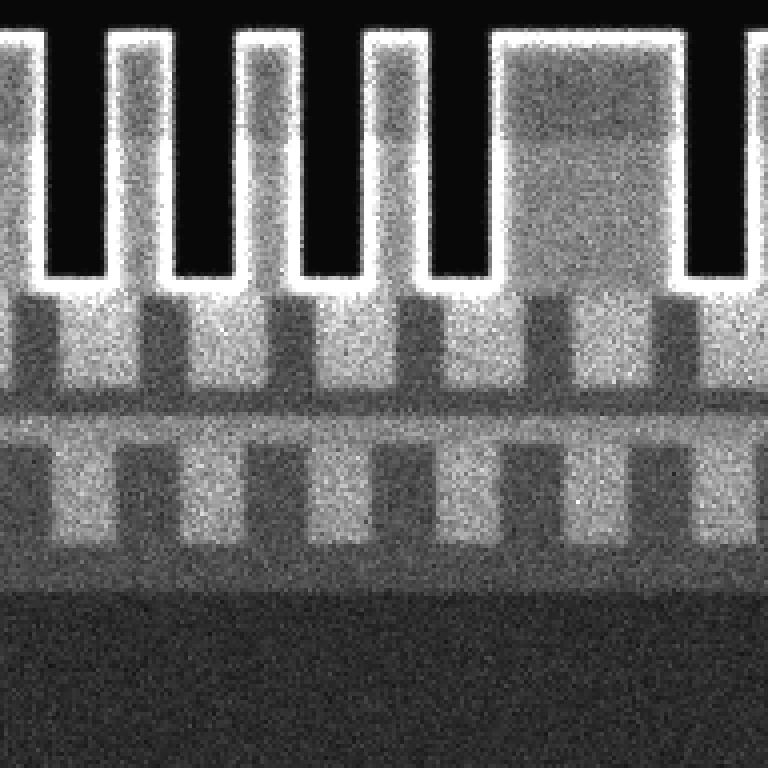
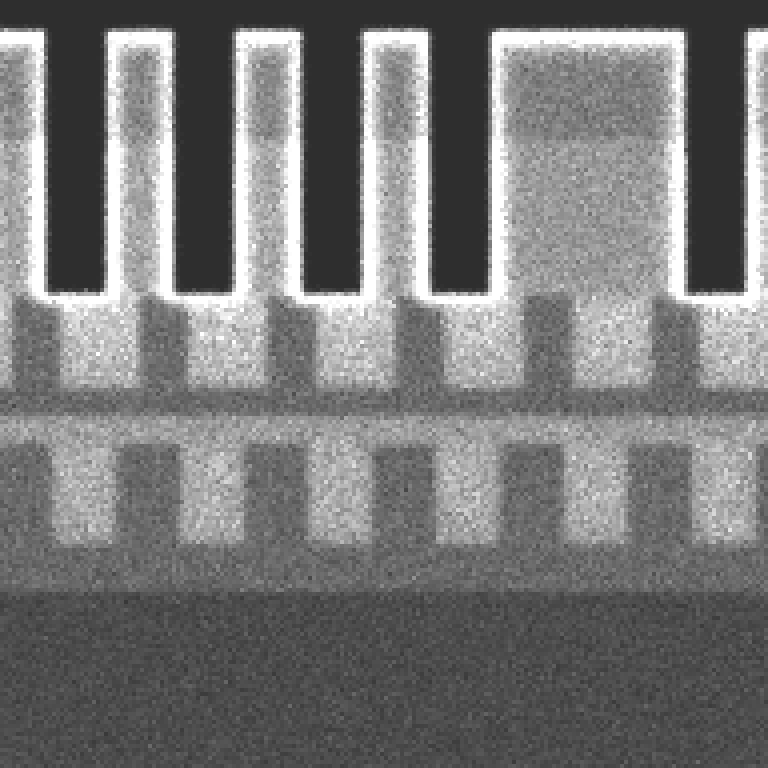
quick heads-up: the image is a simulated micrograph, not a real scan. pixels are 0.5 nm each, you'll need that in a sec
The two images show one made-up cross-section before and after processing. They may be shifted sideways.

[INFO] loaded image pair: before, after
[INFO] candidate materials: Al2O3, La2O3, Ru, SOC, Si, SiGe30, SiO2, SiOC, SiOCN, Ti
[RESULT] removed Al2O3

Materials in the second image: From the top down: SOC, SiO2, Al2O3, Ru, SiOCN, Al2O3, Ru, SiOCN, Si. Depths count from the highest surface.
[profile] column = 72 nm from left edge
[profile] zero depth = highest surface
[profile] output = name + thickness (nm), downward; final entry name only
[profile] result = SOC 54, SiO2 70, Al2O3 8, SiOCN 60, Al2O3 14, SiOCN 74, Si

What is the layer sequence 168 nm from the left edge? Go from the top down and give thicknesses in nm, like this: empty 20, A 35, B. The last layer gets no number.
empty 132, Ru 46, SiOCN 14, Al2O3 14, Ru 50, SiOCN 24, Si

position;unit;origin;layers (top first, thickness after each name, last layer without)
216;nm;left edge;empty 132, SiOCN 60, Al2O3 14, SiOCN 74, Si